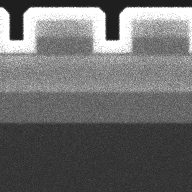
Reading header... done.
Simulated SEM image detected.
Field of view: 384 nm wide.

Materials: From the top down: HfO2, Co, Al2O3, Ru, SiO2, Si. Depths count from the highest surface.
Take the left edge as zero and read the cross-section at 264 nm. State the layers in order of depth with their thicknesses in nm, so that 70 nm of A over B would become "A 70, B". HfO2 24, Co 34, Al2O3 38, Ru 72, SiO2 62, Si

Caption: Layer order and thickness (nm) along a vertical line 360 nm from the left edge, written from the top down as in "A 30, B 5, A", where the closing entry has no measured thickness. HfO2 24, Co 34, Al2O3 38, Ru 72, SiO2 62, Si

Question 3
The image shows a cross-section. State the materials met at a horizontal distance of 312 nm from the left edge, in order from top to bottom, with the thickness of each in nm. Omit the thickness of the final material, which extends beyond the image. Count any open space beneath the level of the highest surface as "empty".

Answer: HfO2 24, Co 34, Al2O3 38, Ru 72, SiO2 62, Si